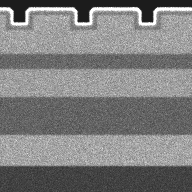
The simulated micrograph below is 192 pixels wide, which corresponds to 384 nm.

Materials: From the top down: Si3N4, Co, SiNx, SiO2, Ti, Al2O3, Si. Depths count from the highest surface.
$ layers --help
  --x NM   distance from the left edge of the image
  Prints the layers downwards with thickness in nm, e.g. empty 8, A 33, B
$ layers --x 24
empty 6, Si3N4 38, Co 48, SiNx 30, SiO2 56, Ti 76, Al2O3 62, Si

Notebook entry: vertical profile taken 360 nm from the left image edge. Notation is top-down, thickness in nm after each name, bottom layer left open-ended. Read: Si3N4 14, Co 78, SiNx 30, SiO2 56, Ti 76, Al2O3 62, Si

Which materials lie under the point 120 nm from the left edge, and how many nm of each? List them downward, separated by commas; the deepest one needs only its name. Si3N4 14, Co 78, SiNx 30, SiO2 56, Ti 76, Al2O3 62, Si